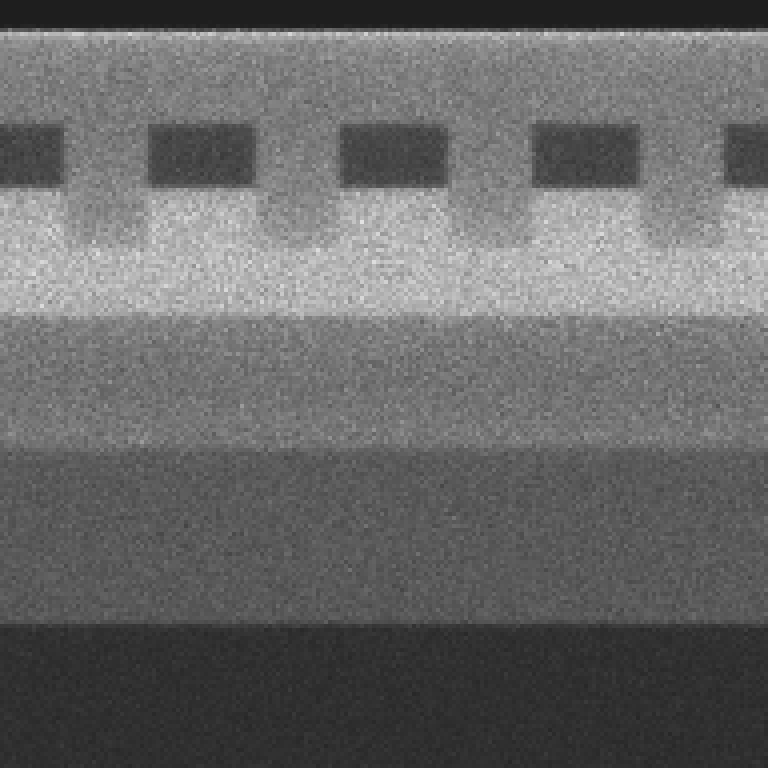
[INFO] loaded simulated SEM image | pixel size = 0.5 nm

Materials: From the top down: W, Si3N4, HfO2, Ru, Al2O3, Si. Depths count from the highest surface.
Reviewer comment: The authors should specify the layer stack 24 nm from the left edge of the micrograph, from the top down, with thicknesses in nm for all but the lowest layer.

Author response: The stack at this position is W 46, Si3N4 32, HfO2 64, Ru 66, Al2O3 88, Si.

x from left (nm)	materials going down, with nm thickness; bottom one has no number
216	W 46, Si3N4 32, HfO2 64, Ru 66, Al2O3 88, Si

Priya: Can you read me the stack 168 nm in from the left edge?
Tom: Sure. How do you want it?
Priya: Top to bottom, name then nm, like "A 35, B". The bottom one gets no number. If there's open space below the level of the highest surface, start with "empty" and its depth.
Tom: W 108, HfO2 34, Ru 66, Al2O3 88, Si